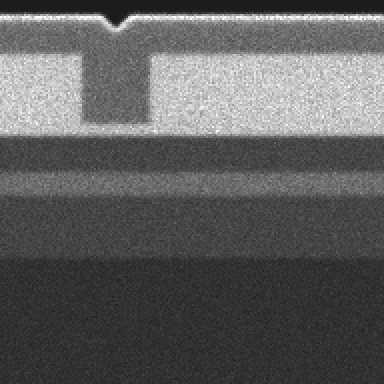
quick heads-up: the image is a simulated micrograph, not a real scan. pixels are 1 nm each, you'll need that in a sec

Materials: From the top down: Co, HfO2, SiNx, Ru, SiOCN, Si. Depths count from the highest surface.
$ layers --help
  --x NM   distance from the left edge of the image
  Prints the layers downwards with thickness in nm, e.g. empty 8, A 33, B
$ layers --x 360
Co 38, HfO2 82, SiNx 36, Ru 24, SiOCN 62, Si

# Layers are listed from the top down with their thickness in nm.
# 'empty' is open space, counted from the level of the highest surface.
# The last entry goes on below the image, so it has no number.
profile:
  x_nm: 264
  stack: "Co 38, HfO2 82, SiNx 36, Ru 24, SiOCN 62, Si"